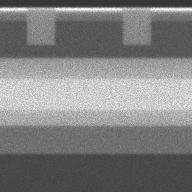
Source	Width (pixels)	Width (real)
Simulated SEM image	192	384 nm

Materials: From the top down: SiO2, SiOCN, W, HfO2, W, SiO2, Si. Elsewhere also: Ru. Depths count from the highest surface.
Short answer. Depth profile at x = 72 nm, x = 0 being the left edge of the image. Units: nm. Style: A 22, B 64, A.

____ Ru 74, SiOCN 26, W 42, HfO2 62, W 32, SiO2 56, Si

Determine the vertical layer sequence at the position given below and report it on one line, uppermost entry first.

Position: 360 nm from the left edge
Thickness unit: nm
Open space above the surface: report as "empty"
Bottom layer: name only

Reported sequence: SiO2 26, SiOCN 74, W 42, HfO2 62, W 32, SiO2 56, Si